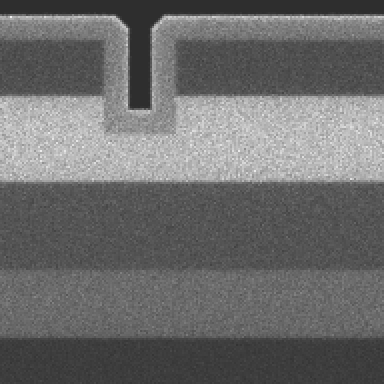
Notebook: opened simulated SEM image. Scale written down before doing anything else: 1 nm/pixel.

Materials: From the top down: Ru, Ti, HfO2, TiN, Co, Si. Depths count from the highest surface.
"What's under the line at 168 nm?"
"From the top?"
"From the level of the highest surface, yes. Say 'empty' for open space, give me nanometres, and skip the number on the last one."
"Ru 118, HfO2 48, TiN 88, Co 68, Si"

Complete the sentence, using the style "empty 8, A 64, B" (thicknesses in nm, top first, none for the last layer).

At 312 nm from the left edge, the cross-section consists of Ru 24, Ti 56, HfO2 86, TiN 88, Co 68, Si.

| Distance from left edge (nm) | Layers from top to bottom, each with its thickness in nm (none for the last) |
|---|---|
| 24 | Ru 24, Ti 56, HfO2 86, TiN 88, Co 68, Si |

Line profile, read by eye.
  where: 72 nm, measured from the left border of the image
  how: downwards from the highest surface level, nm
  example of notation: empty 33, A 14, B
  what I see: Ru 24, Ti 56, HfO2 86, TiN 88, Co 68, Si